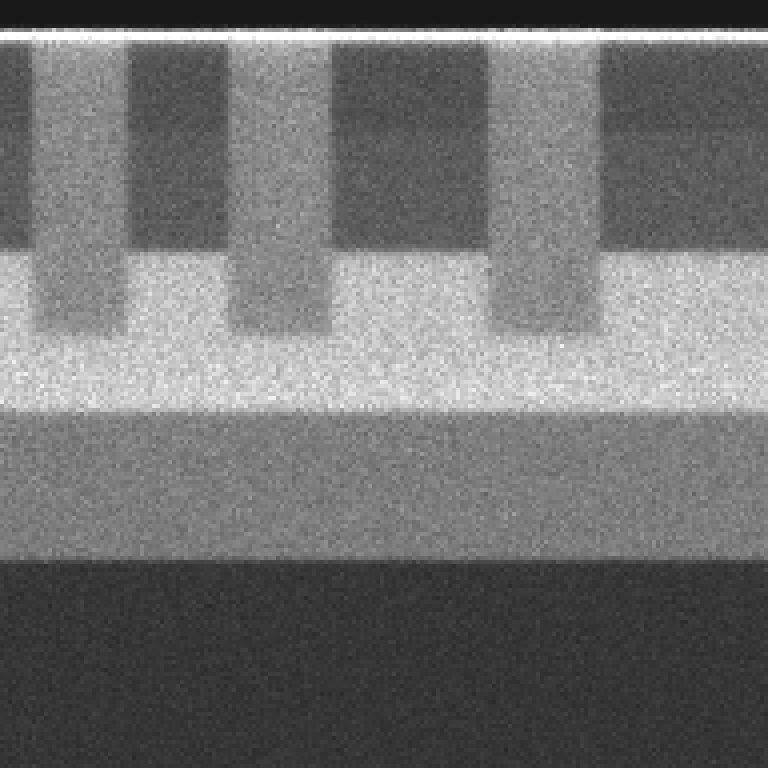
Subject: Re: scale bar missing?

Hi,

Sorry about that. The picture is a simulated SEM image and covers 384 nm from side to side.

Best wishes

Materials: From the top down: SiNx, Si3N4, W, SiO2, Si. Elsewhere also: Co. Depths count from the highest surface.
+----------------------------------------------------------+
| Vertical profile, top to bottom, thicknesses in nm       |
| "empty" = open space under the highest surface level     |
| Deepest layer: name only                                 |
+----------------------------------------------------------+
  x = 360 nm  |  SiNx 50, Si3N4 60, W 80, SiO2 74, Si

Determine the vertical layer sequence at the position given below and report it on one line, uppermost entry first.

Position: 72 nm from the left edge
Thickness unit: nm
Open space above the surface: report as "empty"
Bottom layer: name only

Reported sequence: SiNx 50, Si3N4 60, W 80, SiO2 74, Si